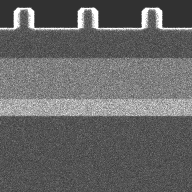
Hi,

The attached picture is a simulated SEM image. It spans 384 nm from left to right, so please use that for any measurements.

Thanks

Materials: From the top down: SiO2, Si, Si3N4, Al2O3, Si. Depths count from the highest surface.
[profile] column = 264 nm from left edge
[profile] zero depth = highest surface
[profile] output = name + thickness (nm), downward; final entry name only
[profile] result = empty 40, Si 60, Si3N4 82, Al2O3 34, Si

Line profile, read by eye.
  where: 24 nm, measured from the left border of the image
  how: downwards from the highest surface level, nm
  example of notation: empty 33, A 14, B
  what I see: empty 40, Si 60, Si3N4 82, Al2O3 34, Si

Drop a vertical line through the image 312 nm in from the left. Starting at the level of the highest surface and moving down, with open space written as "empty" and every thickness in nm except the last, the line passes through SiO2 40, Si 60, Si3N4 82, Al2O3 34, Si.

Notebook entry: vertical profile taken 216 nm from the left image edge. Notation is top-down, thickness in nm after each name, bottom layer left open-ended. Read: empty 40, Si 60, Si3N4 82, Al2O3 34, Si